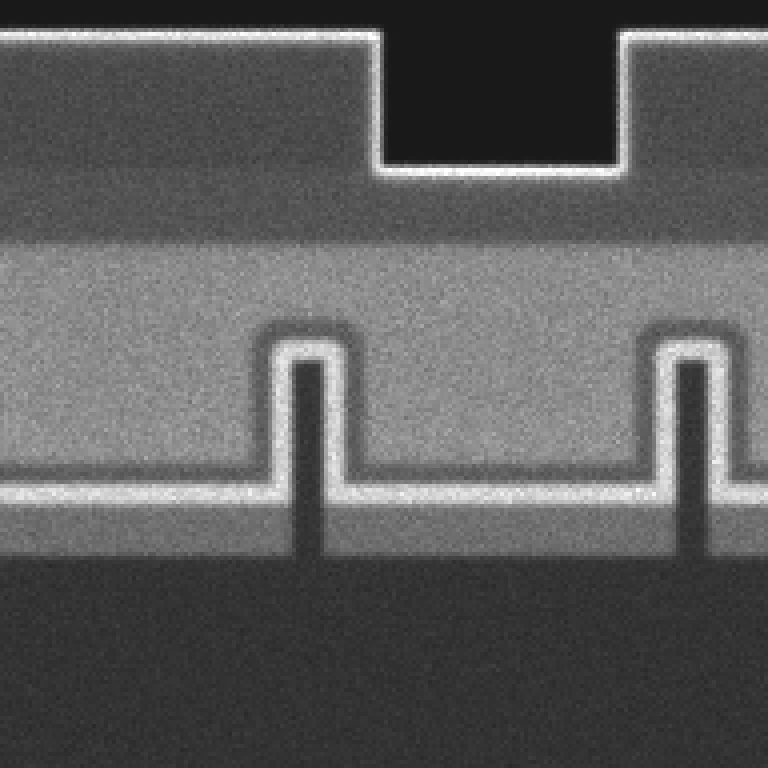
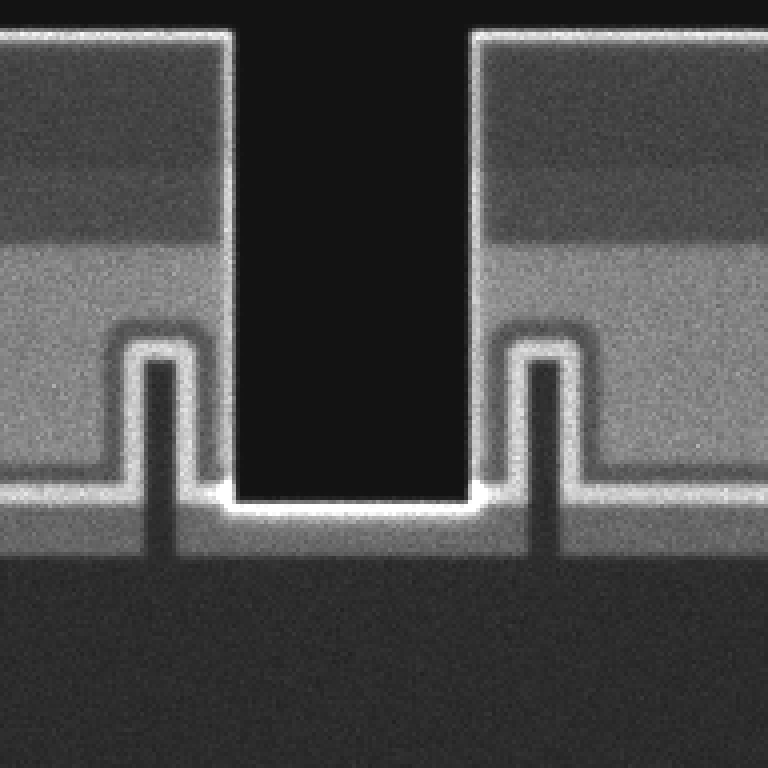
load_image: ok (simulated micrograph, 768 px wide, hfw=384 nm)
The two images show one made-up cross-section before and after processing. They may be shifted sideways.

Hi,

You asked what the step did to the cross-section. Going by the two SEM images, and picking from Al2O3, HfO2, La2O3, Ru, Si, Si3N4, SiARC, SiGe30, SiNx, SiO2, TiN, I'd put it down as HfO2 and Ru and Si3N4 and TiN, removed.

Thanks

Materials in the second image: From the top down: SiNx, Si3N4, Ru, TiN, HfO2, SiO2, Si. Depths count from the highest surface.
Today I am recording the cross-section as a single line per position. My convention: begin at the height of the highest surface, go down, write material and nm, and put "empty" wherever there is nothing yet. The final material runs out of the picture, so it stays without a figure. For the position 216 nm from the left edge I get empty 236, SiO2 26, Si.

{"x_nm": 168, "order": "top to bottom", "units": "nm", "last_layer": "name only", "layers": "empty 236, SiO2 26, Si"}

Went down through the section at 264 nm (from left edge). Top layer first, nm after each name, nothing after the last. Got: SiNx 68, Si3N4 38, Ru 38, TiN 10, HfO2 10, Si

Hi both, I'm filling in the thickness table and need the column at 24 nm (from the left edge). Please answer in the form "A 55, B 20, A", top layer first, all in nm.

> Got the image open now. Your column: SiNx 68, Si3N4 38, Ru 110, TiN 10, HfO2 10, SiO2 26, Si